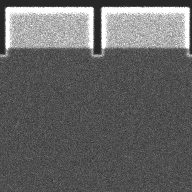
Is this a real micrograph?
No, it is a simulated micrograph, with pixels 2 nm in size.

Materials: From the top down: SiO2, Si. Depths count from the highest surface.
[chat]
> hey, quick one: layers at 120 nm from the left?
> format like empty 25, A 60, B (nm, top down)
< SiO2 80, Si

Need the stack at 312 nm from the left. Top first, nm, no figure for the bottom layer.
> SiO2 80, Si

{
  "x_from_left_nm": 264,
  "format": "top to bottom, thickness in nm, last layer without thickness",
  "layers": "SiO2 80, Si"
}